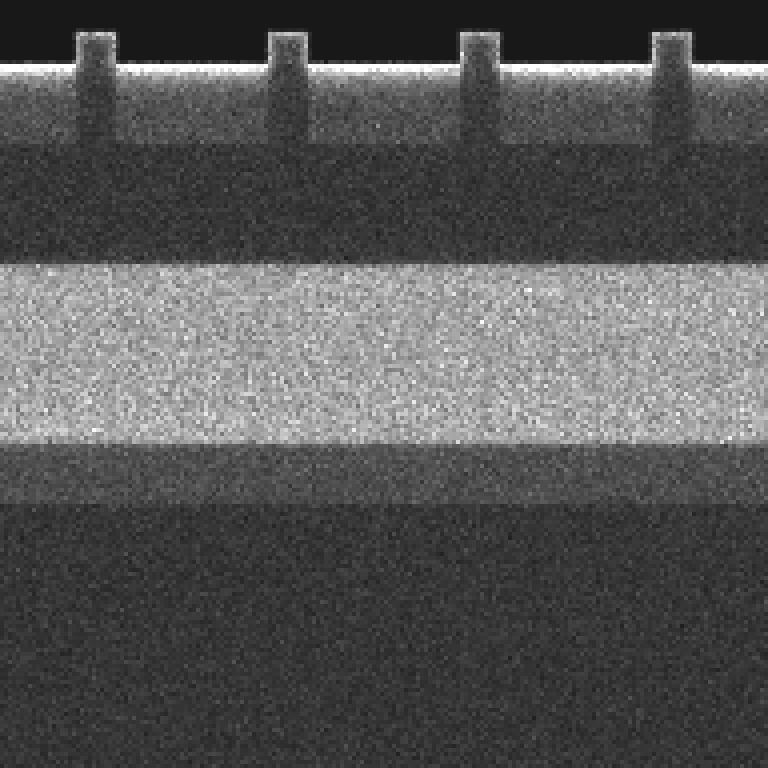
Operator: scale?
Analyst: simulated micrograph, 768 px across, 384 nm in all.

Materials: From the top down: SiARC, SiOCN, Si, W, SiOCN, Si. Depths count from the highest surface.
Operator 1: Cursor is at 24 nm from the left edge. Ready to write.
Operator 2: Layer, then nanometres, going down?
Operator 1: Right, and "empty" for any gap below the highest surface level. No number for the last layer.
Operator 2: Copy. empty 16, SiARC 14, SiOCN 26, Si 60, W 90, SiOCN 30, Si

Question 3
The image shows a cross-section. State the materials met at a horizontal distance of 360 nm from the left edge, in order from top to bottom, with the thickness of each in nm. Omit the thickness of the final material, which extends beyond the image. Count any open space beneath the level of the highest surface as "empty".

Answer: empty 16, SiARC 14, SiOCN 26, Si 60, W 90, SiOCN 30, Si